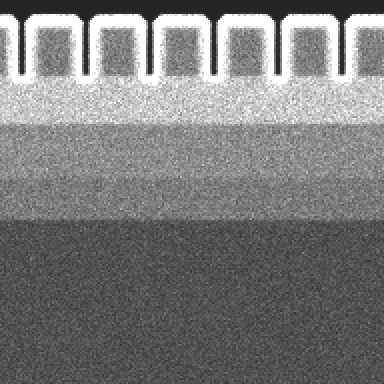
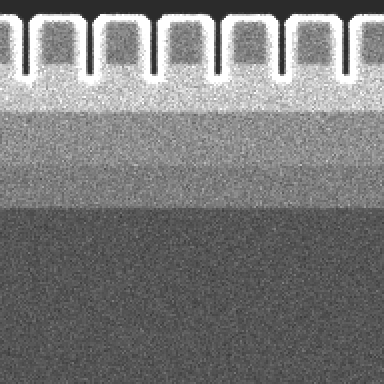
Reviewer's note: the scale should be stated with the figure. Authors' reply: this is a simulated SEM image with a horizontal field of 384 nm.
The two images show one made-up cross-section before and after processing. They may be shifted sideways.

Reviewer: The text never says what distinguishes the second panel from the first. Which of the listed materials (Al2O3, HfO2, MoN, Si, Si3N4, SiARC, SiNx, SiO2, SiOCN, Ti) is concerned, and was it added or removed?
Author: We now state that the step removed SiO2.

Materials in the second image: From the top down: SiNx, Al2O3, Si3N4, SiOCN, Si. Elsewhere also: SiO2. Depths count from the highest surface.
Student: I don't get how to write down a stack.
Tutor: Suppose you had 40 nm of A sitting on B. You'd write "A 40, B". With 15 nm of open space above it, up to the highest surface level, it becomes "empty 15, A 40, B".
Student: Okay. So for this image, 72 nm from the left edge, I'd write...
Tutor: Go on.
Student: SiNx 48, Al2O3 48, Si3N4 54, SiOCN 42, Si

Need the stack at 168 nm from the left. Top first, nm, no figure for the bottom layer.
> SiO2 60, Al2O3 36, Si3N4 54, SiOCN 42, Si